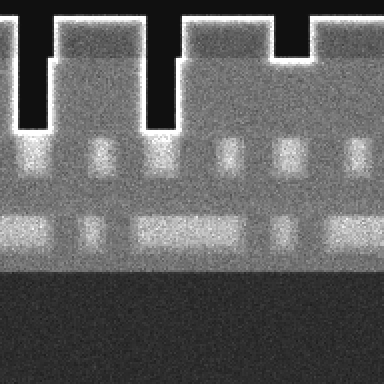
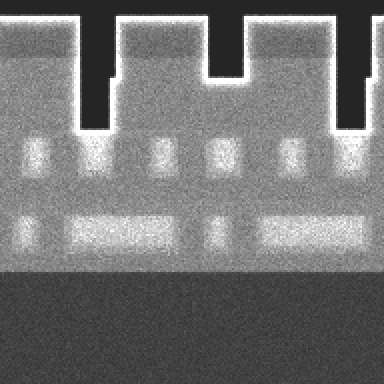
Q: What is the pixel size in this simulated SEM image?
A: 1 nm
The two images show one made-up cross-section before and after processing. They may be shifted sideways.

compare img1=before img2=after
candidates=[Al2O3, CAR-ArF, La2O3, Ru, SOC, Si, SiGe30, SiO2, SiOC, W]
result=removed:SiO2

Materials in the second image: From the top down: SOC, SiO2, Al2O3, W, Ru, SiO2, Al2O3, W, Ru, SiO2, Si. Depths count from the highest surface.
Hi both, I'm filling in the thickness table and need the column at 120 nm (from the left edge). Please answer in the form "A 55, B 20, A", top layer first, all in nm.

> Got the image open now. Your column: SOC 42, SiO2 72, Al2O3 8, SiO2 62, Al2O3 16, W 30, Ru 8, SiO2 18, Si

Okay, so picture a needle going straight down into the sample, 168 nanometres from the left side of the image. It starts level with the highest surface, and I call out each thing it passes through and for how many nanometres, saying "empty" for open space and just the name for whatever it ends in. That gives SOC 42, SiO2 72, Al2O3 8, W 32, Ru 8, SiO2 22, Al2O3 16, W 30, Ru 8, SiO2 18, Si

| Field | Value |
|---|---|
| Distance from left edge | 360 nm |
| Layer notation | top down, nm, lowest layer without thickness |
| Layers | empty 114, Al2O3 8, W 32, Ru 8, SiO2 22, Al2O3 16, W 30, Ru 8, SiO2 18, Si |